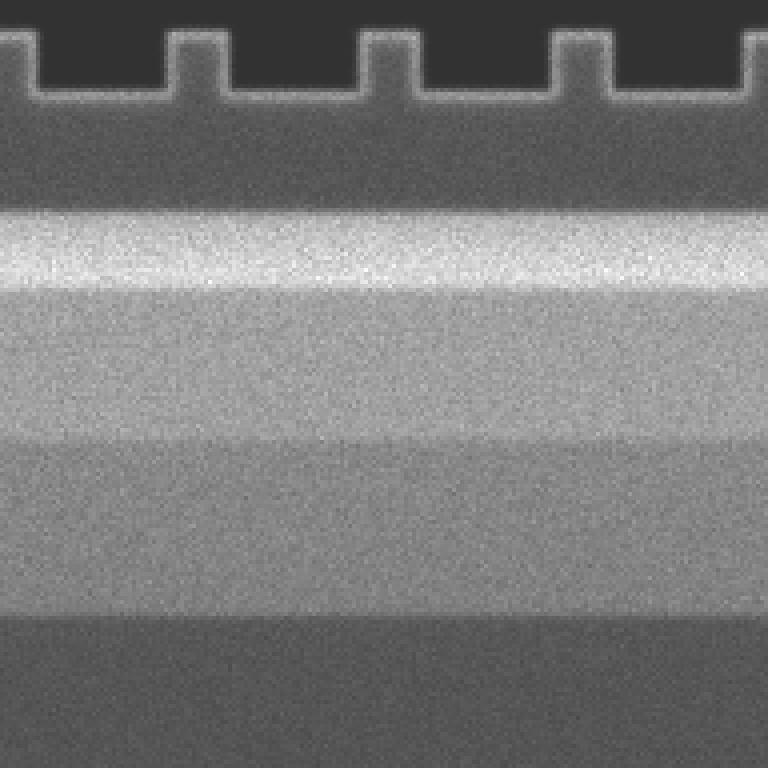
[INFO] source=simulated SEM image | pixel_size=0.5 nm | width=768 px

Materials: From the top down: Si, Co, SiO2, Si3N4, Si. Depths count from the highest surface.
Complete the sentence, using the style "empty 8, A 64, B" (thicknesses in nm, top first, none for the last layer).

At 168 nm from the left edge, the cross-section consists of empty 30, Si 60, Co 38, SiO2 76, Si3N4 88, Si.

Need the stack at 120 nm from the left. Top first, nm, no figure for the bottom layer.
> empty 30, Si 60, Co 38, SiO2 76, Si3N4 88, Si